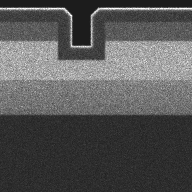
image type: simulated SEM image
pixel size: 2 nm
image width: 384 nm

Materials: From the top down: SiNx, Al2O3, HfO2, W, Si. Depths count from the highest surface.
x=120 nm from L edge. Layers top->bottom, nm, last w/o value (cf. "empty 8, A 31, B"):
SiNx 104, HfO2 40, W 70, Si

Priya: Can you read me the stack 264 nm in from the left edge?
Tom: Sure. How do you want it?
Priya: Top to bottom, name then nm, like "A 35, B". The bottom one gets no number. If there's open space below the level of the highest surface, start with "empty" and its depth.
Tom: SiNx 28, Al2O3 38, HfO2 78, W 70, Si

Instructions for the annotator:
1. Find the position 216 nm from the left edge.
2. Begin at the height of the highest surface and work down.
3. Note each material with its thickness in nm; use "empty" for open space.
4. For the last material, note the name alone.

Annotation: SiNx 28, Al2O3 38, HfO2 78, W 70, Si